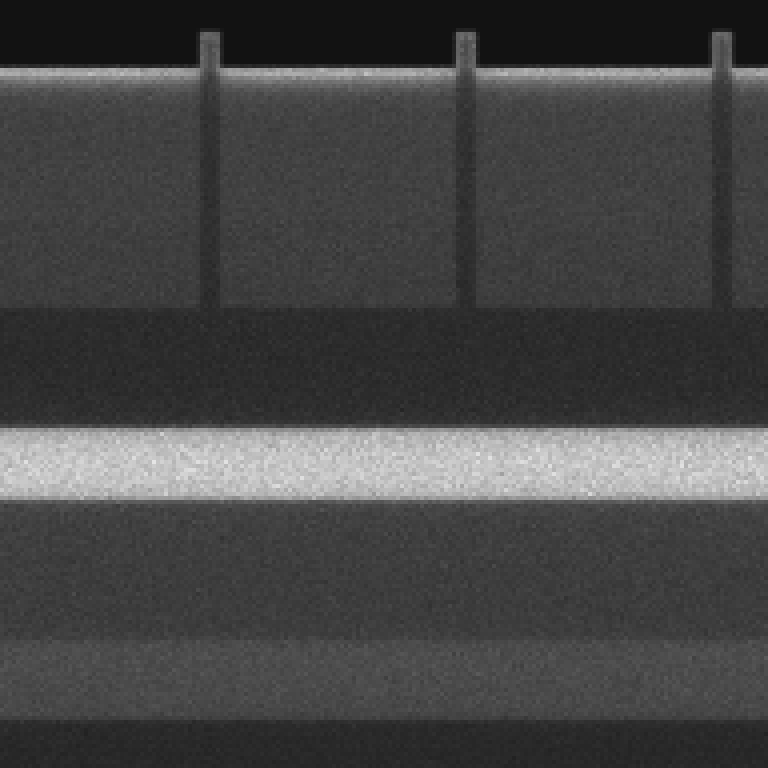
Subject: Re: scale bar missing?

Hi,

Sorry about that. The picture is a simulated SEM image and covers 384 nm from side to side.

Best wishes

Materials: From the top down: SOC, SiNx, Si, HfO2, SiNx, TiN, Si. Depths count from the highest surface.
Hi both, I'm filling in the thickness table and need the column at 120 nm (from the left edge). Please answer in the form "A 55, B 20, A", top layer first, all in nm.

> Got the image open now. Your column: empty 18, SOC 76, SiNx 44, Si 60, HfO2 36, SiNx 70, TiN 40, Si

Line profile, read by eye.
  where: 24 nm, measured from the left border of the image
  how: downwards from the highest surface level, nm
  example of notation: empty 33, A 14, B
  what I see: empty 18, SOC 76, SiNx 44, Si 60, HfO2 36, SiNx 70, TiN 40, Si